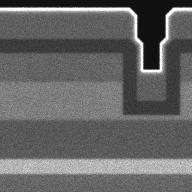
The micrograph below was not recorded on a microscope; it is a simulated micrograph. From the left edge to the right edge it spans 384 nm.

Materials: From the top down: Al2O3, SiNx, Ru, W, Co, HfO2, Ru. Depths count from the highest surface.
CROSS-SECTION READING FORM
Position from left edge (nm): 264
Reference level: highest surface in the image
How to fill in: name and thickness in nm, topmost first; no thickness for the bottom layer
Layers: empty 6, Al2O3 62, SiNx 146, W 10, Co 78, HfO2 30, Ru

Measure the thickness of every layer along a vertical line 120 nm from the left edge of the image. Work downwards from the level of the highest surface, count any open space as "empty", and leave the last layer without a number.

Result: Al2O3 62, SiNx 28, Ru 58, W 76, Co 78, HfO2 30, Ru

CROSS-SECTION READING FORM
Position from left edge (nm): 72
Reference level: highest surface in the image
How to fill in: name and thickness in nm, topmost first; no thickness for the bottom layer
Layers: Al2O3 62, SiNx 28, Ru 58, W 76, Co 78, HfO2 30, Ru